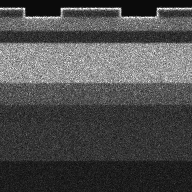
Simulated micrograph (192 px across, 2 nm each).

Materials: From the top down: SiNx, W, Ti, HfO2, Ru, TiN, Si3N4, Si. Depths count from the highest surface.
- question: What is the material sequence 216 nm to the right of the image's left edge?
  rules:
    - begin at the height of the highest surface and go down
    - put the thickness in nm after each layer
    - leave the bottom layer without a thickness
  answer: SiNx 18, W 28, Ti 24, HfO2 80, Ru 44, TiN 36, Si3N4 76, Si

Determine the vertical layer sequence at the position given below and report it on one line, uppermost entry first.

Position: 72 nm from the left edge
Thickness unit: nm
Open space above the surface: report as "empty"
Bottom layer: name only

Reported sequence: empty 18, W 28, Ti 24, HfO2 80, Ru 44, TiN 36, Si3N4 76, Si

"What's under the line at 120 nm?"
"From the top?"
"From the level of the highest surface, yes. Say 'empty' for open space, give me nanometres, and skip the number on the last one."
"empty 18, W 28, Ti 24, HfO2 80, Ru 44, TiN 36, Si3N4 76, Si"